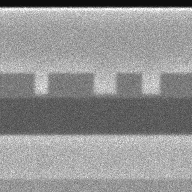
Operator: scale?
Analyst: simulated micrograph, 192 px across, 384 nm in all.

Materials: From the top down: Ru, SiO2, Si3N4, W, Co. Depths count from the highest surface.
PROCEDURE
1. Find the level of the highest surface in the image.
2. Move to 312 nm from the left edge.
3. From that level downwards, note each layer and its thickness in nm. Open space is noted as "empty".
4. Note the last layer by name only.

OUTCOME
Ru 172, SiO2 8, Si3N4 74, W 88, Co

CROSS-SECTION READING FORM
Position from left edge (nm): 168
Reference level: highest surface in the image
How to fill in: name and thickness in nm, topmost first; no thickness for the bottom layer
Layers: Ru 130, SiO2 50, Si3N4 74, W 88, Co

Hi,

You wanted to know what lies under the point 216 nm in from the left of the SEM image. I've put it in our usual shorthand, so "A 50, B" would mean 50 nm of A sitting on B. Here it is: Ru 172, SiO2 8, Si3N4 74, W 88, Co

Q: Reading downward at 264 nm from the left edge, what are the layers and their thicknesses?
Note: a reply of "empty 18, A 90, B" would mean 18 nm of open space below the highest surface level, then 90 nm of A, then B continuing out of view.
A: Ru 130, SiO2 50, Si3N4 74, W 88, Co